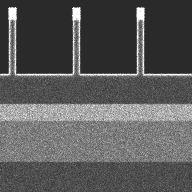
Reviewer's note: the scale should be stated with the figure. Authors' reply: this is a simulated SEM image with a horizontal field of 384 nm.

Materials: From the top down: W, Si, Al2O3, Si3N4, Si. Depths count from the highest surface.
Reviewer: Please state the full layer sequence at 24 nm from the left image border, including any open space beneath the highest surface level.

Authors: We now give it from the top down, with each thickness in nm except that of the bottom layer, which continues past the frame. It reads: W 24, Si 168, Al2O3 34, Si3N4 82, Si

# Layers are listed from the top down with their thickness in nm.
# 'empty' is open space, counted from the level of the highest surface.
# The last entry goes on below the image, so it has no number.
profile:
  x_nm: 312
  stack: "empty 132, Si 60, Al2O3 34, Si3N4 82, Si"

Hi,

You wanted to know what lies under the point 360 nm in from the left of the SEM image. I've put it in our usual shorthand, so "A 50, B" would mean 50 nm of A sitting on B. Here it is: empty 132, Si 60, Al2O3 34, Si3N4 82, Si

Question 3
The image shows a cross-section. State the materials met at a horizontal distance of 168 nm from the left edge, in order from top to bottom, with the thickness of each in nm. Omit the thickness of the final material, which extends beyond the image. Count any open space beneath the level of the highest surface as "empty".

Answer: empty 132, Si 60, Al2O3 34, Si3N4 82, Si